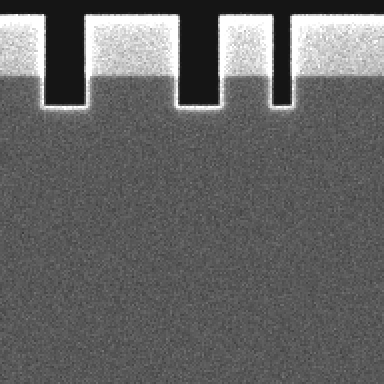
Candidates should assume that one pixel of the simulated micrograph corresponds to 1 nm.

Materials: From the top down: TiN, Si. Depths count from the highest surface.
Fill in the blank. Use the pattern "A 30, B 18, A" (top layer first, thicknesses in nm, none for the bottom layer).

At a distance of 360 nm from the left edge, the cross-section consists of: TiN 60, Si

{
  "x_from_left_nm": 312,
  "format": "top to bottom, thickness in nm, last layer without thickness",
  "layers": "TiN 60, Si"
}